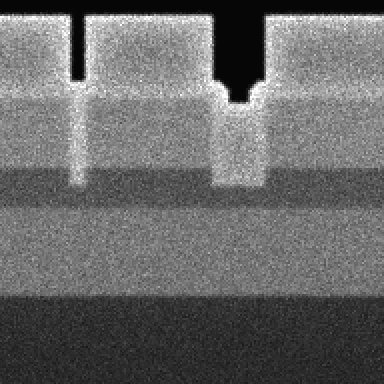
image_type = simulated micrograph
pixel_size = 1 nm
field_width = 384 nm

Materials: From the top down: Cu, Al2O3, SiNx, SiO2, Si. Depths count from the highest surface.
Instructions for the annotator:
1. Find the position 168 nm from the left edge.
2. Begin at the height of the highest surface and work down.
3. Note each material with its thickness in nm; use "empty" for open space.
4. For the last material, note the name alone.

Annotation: Cu 82, Al2O3 70, SiNx 40, SiO2 88, Si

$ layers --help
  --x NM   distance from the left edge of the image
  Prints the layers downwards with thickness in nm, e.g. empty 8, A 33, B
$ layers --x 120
Cu 82, Al2O3 70, SiNx 40, SiO2 88, Si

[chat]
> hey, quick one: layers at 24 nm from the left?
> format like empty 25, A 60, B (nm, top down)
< Cu 82, Al2O3 70, SiNx 40, SiO2 88, Si